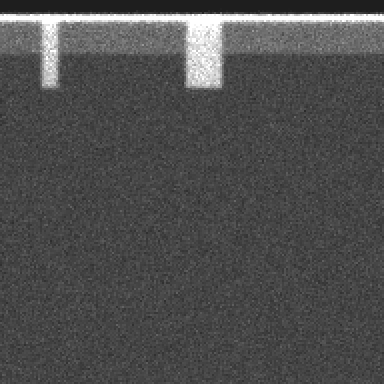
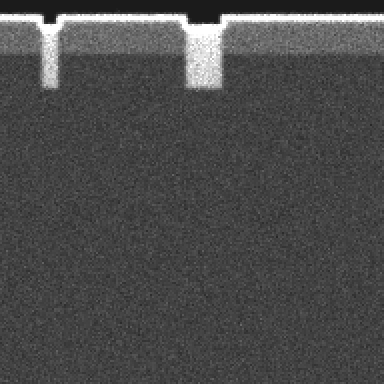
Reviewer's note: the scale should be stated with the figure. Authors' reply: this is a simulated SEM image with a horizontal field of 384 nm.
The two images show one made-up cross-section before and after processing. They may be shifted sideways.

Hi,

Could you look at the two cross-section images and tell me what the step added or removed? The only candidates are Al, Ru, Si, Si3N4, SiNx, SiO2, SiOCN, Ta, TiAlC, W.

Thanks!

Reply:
removed W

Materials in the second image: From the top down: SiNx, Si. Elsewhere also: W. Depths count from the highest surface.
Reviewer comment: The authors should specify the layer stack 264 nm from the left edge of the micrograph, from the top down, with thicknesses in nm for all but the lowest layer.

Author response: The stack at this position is SiNx 38, Si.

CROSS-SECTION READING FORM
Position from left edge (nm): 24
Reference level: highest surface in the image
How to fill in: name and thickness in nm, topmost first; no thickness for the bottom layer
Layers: SiNx 38, Si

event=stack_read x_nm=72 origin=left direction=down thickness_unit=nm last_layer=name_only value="SiNx 38, Si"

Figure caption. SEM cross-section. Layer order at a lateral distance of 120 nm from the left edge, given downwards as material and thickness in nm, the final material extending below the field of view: SiNx 38, Si